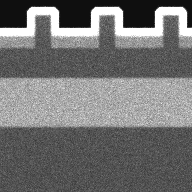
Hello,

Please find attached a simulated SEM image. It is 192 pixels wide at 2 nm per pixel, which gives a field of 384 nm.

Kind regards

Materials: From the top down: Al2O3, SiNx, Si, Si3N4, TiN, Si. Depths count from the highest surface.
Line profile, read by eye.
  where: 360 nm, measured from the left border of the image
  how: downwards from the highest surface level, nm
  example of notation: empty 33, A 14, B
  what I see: Al2O3 56, SiNx 24, Si 60, Si3N4 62, TiN 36, Si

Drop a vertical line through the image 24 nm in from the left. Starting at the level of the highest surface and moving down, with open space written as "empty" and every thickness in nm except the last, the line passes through empty 42, Al2O3 14, SiNx 24, Si 60, Si3N4 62, TiN 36, Si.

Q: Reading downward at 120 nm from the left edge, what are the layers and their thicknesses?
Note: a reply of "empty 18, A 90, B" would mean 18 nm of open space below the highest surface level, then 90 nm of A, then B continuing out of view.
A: empty 42, Al2O3 14, SiNx 24, Si 60, Si3N4 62, TiN 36, Si